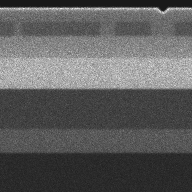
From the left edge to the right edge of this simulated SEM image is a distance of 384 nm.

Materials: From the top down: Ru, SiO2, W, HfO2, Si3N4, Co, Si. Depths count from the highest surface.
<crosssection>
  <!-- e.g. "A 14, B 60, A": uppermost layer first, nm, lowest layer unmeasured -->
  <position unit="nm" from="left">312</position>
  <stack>Ru 56, W 44, HfO2 62, Si3N4 80, Co 48, Si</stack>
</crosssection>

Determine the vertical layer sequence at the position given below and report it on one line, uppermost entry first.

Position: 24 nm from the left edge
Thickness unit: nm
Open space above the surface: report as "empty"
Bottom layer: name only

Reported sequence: Ru 28, SiO2 28, W 44, HfO2 62, Si3N4 80, Co 48, Si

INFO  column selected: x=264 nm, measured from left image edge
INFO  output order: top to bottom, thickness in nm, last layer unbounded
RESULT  Ru 28, SiO2 28, W 44, HfO2 62, Si3N4 80, Co 48, Si